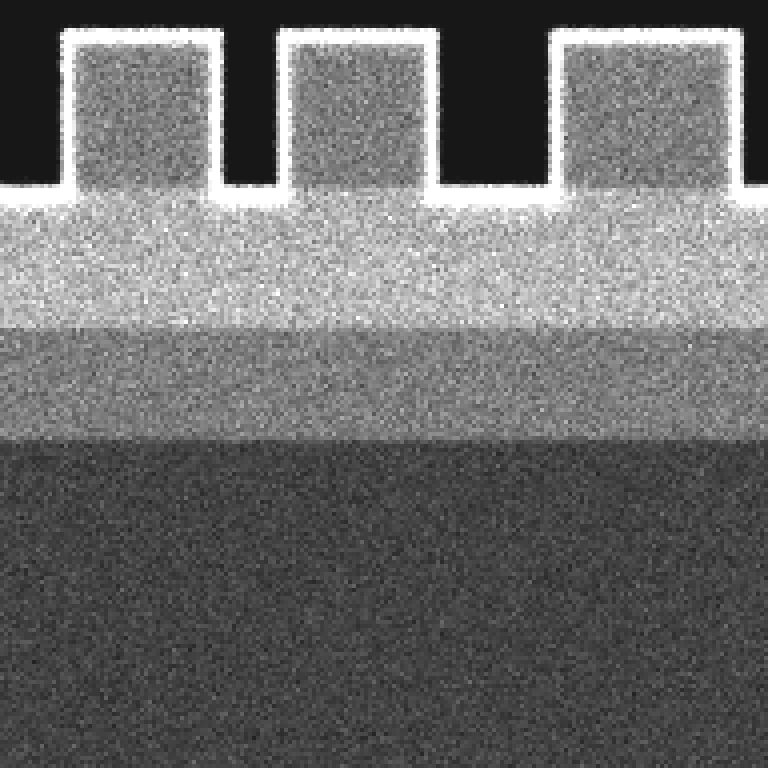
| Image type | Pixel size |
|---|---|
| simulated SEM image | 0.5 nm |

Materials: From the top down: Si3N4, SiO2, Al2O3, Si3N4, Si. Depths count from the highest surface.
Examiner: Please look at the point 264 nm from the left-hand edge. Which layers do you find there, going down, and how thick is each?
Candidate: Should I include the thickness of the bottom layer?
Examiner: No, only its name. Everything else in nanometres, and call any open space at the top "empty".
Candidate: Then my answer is empty 78, SiO2 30, Al2O3 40, Si3N4 56, Si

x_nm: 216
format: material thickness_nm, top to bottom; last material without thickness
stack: Si3N4 78, SiO2 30, Al2O3 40, Si3N4 56, Si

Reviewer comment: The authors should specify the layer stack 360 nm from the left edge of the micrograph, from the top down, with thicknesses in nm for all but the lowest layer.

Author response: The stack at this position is Si3N4 78, SiO2 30, Al2O3 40, Si3N4 56, Si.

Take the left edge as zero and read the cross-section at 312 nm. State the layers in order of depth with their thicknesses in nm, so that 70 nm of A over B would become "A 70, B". Si3N4 78, SiO2 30, Al2O3 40, Si3N4 56, Si